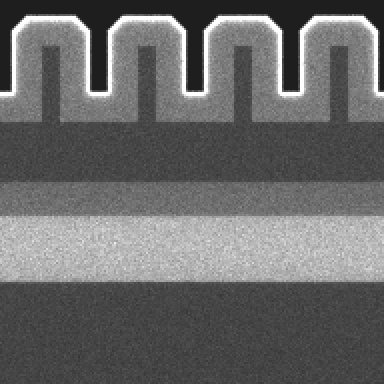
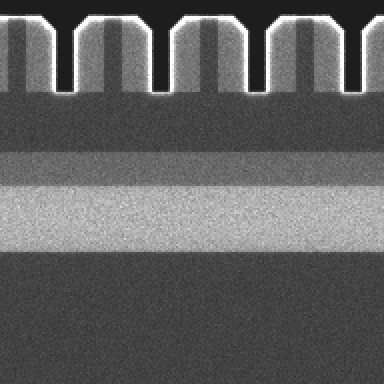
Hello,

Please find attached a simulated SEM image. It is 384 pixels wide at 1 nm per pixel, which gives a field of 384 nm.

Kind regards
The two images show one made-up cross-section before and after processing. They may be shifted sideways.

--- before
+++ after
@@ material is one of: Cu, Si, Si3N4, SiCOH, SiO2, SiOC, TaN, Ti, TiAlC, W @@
Si3N4 removed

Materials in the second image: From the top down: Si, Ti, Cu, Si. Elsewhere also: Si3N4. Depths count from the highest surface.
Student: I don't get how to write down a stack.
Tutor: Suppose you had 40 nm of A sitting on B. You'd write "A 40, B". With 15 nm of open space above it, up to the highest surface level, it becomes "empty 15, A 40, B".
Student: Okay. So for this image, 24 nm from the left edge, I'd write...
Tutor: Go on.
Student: Si 136, Ti 34, Cu 66, Si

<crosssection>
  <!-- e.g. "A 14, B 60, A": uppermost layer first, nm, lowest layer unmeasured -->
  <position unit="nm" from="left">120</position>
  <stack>Si 136, Ti 34, Cu 66, Si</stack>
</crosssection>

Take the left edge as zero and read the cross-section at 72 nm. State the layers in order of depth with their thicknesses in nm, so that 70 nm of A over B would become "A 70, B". empty 76, Si 60, Ti 34, Cu 66, Si